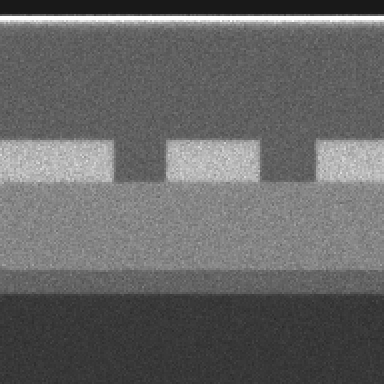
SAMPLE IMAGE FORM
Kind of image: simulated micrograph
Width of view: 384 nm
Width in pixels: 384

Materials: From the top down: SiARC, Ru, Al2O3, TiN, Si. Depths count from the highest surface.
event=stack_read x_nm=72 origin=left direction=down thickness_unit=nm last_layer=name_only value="SiARC 124, Ru 42, Al2O3 88, TiN 24, Si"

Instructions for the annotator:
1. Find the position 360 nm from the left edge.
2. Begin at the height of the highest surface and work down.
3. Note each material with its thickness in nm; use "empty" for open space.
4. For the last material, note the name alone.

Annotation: SiARC 124, Ru 42, Al2O3 88, TiN 24, Si